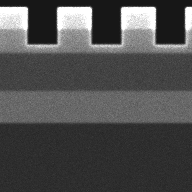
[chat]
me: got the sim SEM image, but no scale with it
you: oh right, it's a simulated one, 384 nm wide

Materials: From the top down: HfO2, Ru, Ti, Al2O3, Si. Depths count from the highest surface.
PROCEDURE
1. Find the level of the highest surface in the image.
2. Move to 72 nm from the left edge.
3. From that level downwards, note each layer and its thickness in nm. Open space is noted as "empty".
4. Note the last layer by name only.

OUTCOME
empty 74, Ru 16, Ti 76, Al2O3 64, Si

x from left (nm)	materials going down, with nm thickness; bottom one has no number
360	empty 74, Ru 16, Ti 76, Al2O3 64, Si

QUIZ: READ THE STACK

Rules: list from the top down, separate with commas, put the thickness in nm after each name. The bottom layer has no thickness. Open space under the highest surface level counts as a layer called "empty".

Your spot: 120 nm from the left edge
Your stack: HfO2 42, Ru 48, Ti 76, Al2O3 64, Si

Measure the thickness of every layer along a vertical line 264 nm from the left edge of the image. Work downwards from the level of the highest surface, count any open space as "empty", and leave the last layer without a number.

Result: HfO2 42, Ru 48, Ti 76, Al2O3 64, Si